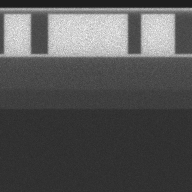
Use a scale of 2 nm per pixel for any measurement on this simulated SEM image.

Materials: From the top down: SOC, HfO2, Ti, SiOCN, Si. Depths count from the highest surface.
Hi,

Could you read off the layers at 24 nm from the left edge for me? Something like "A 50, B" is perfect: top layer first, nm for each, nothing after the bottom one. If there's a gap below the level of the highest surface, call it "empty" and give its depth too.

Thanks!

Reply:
SOC 12, HfO2 86, Ti 66, SiOCN 38, Si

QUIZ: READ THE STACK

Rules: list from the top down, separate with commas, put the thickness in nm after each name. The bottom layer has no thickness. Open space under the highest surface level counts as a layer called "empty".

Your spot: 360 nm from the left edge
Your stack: SOC 92, HfO2 6, Ti 66, SiOCN 38, Si